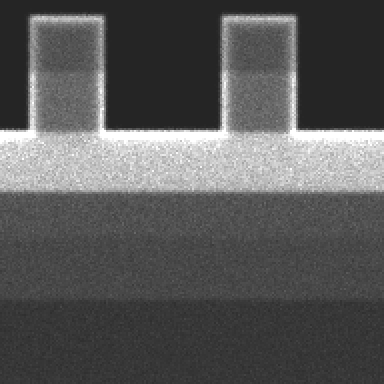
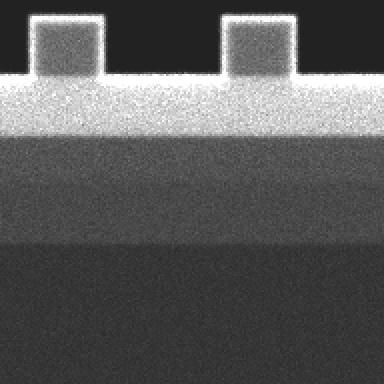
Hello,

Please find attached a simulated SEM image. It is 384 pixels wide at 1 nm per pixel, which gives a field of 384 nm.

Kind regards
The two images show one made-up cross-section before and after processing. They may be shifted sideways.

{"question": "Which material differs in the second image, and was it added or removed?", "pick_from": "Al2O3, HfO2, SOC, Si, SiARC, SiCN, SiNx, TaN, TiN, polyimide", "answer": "SOC, removed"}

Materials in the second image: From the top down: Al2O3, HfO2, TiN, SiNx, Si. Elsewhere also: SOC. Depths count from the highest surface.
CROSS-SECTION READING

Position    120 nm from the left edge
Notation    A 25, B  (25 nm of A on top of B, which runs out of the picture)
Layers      empty 60, HfO2 60, TiN 46, SiNx 62, Si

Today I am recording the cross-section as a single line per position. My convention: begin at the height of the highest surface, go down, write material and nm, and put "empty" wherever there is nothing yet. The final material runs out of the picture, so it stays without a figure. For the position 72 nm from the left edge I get Al2O3 60, HfO2 60, TiN 46, SiNx 62, Si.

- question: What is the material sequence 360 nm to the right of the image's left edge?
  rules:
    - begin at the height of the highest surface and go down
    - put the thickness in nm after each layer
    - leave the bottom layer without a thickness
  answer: empty 60, HfO2 60, TiN 46, SiNx 62, Si